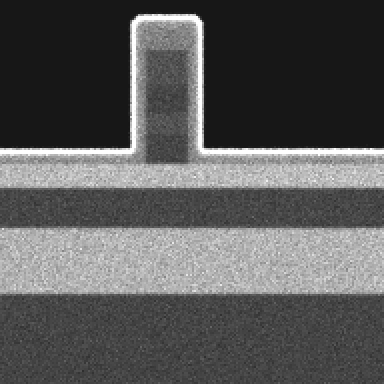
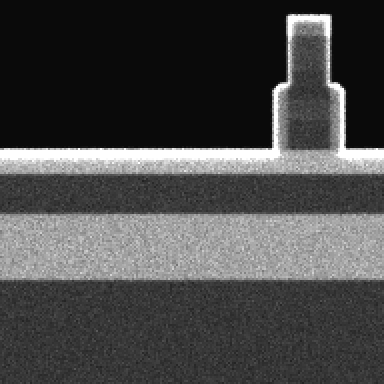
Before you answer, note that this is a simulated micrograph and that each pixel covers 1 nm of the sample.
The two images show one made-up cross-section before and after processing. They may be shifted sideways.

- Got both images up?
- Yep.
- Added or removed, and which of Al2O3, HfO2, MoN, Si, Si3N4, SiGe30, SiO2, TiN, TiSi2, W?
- removed, TiN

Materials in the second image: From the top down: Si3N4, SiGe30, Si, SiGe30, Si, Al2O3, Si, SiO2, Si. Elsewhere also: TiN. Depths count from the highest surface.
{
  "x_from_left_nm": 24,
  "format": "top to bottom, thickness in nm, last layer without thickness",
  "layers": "empty 134, Al2O3 24, Si 40, SiO2 66, Si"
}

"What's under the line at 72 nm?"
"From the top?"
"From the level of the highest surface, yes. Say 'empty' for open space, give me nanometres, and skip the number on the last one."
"empty 134, Al2O3 24, Si 40, SiO2 66, Si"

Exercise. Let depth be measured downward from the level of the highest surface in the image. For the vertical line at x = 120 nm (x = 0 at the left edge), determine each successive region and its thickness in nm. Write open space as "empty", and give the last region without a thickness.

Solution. empty 134, Al2O3 24, Si 40, SiO2 66, Si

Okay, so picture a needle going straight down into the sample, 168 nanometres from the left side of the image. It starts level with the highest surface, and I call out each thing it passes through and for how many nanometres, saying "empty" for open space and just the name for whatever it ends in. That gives empty 134, Al2O3 24, Si 40, SiO2 66, Si